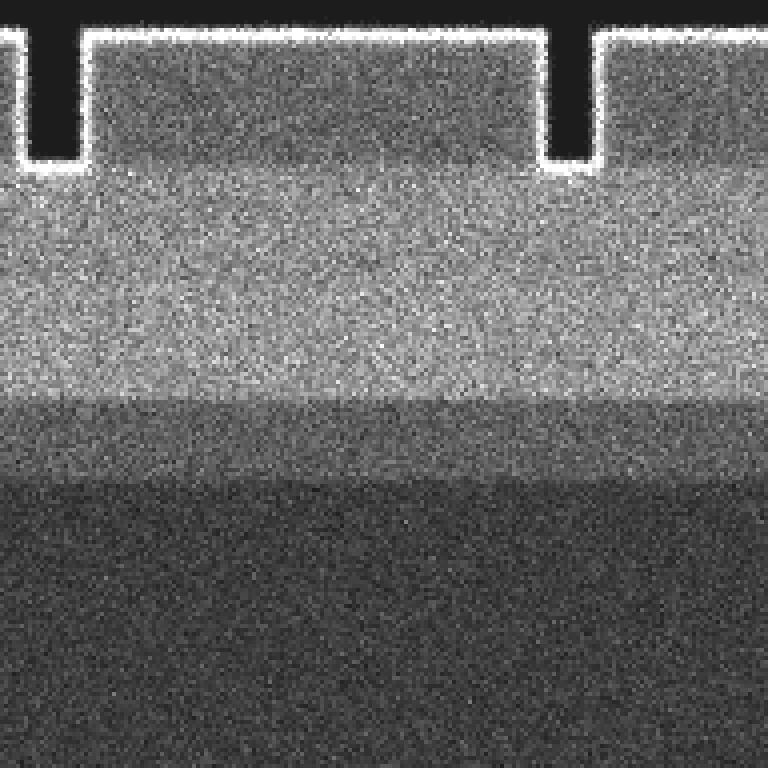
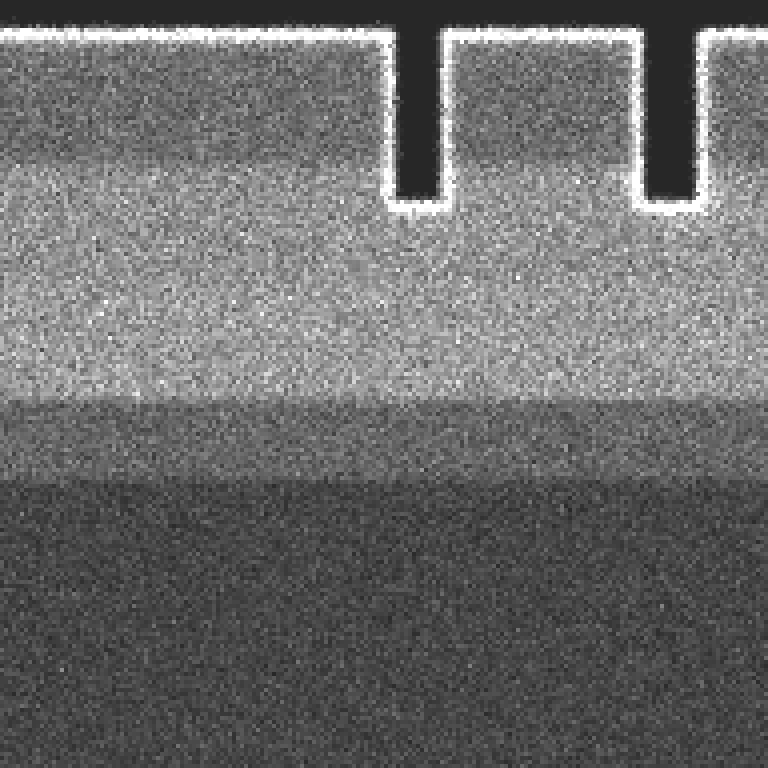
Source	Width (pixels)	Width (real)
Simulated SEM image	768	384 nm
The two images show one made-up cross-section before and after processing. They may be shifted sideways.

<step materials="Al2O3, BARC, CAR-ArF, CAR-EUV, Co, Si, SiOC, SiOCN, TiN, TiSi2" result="removed Co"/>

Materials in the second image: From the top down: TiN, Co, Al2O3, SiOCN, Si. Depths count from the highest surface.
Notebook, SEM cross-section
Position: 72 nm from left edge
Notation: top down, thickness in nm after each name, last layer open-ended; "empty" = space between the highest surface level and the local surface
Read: TiN 66, Co 58, Al2O3 60, SiOCN 40, Si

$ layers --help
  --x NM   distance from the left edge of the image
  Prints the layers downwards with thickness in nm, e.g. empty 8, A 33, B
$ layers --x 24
TiN 66, Co 58, Al2O3 60, SiOCN 40, Si